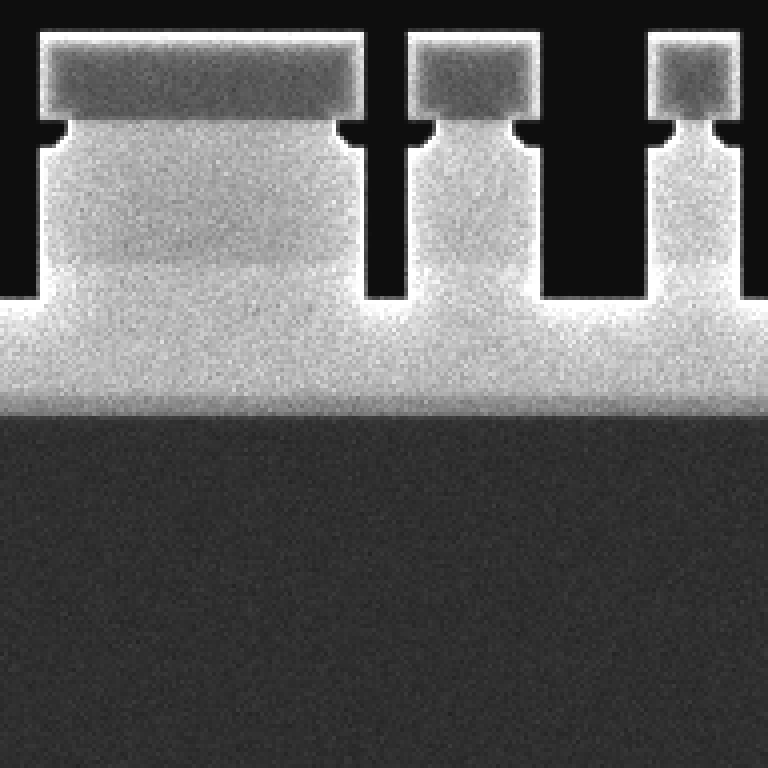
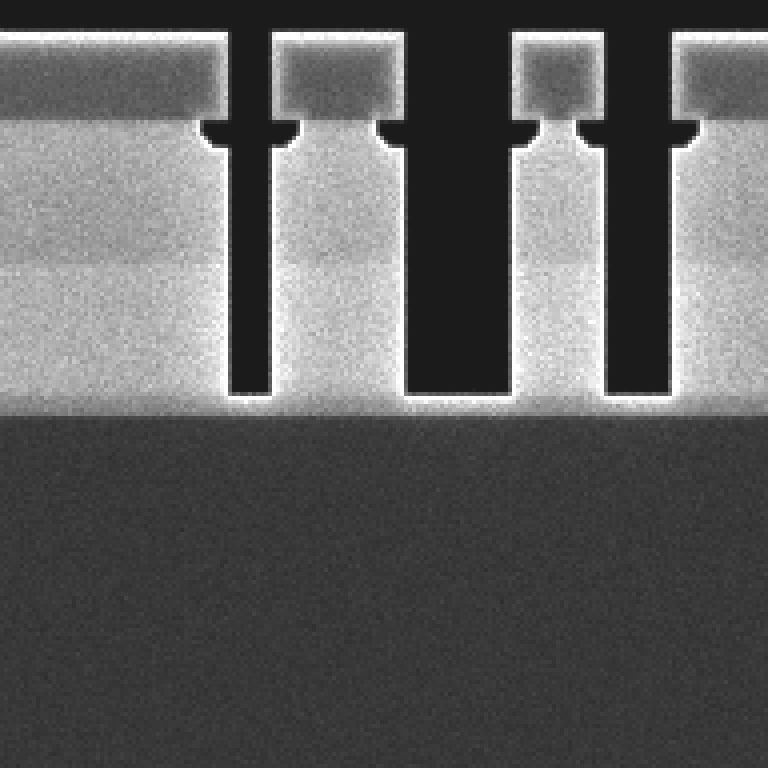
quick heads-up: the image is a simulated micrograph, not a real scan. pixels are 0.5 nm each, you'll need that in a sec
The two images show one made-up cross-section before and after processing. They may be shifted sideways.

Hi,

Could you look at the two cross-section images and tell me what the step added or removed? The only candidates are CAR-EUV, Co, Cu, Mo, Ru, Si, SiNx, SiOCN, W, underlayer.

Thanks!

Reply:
removed W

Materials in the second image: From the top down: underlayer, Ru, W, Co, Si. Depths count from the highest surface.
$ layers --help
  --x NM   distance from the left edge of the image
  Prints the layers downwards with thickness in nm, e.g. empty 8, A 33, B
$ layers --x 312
empty 182, Co 10, Si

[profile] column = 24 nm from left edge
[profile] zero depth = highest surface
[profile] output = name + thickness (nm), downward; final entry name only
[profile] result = underlayer 44, Ru 72, W 66, Co 10, Si